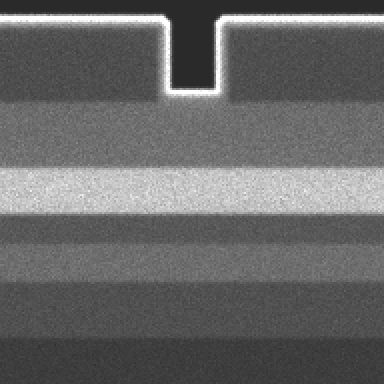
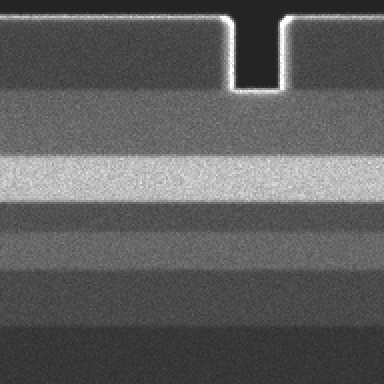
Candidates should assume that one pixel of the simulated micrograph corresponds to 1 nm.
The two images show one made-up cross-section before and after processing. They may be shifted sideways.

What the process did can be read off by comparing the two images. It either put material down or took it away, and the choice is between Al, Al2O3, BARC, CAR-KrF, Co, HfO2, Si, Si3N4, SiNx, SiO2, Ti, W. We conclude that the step removed Al2O3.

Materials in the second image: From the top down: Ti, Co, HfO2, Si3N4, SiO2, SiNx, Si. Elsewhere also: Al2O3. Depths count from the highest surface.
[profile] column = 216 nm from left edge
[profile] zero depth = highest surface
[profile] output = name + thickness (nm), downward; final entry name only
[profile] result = Ti 74, Co 66, HfO2 46, Si3N4 30, SiO2 38, SiNx 56, Si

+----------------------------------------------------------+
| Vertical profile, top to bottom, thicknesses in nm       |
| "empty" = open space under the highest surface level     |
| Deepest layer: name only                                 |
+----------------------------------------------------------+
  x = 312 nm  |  Ti 74, Co 66, HfO2 46, Si3N4 30, SiO2 38, SiNx 56, Si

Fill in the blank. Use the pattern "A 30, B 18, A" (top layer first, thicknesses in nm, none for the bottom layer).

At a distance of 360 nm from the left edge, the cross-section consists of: Ti 74, Co 66, HfO2 46, Si3N4 30, SiO2 38, SiNx 56, Si